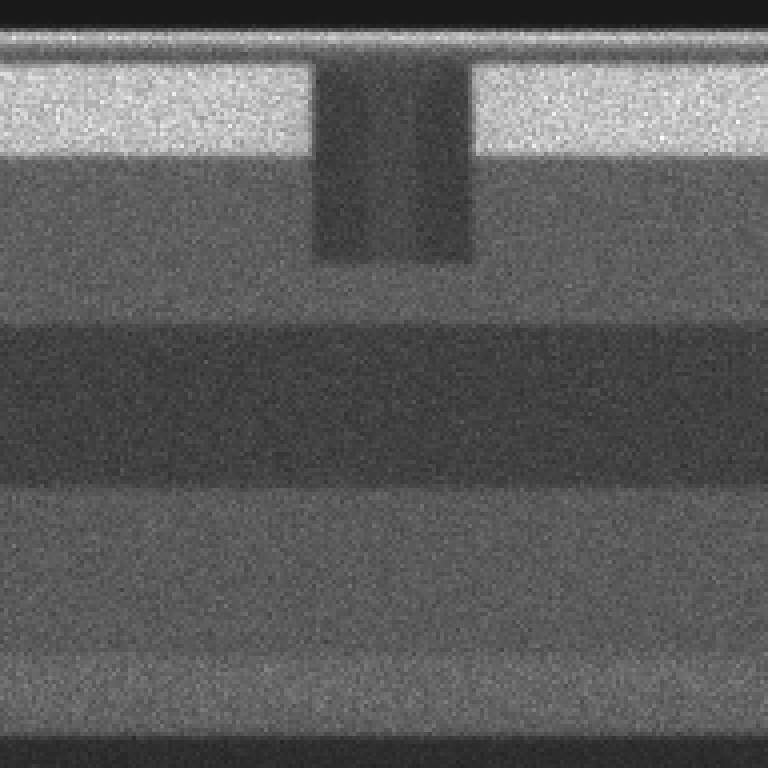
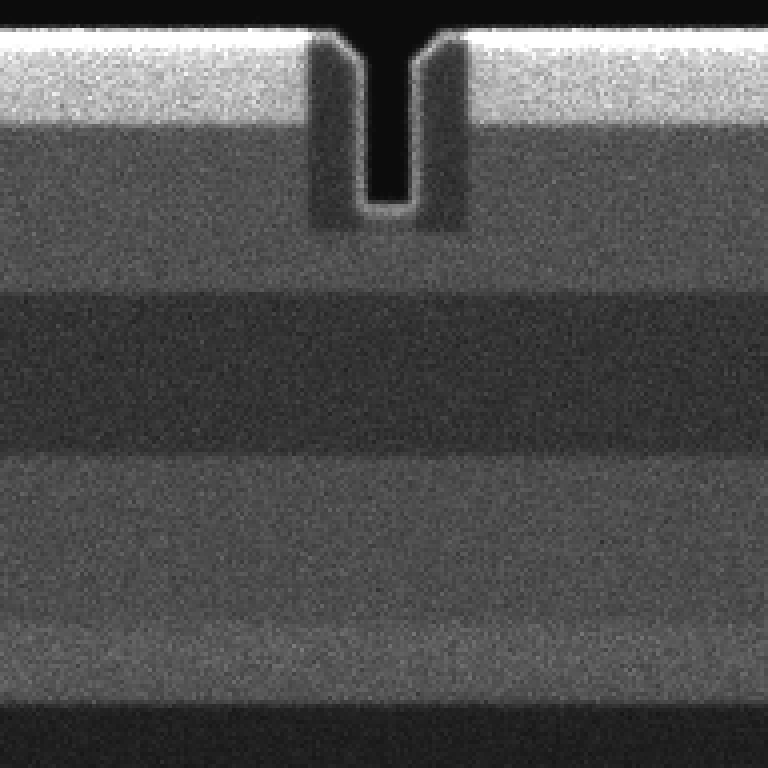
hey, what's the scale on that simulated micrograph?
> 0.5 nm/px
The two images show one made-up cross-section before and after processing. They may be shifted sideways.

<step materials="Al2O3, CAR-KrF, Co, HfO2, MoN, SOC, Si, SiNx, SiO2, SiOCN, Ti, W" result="removed SOC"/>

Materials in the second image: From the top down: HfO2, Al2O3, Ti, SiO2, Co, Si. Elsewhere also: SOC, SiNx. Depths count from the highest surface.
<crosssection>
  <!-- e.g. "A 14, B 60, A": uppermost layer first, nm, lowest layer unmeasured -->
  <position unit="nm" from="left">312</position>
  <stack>HfO2 46, Al2O3 84, Ti 82, SiO2 84, Co 40, Si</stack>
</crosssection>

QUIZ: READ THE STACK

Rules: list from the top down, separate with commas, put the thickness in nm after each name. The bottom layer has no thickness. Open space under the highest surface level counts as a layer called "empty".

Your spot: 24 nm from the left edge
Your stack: HfO2 46, Al2O3 84, Ti 82, SiO2 84, Co 40, Si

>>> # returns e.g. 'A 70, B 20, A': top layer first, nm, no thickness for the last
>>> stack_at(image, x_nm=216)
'empty 4, SiNx 96, Al2O3 30, Ti 82, SiO2 84, Co 40, Si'